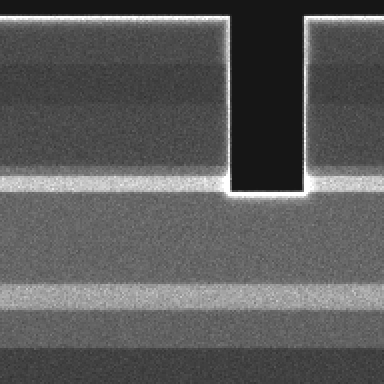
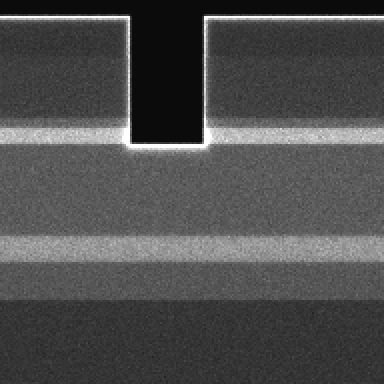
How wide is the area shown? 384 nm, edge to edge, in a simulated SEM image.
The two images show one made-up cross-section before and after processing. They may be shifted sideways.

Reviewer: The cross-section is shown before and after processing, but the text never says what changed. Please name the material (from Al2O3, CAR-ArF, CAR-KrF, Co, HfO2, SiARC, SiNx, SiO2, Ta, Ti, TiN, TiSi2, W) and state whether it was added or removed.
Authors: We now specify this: SiARC, removed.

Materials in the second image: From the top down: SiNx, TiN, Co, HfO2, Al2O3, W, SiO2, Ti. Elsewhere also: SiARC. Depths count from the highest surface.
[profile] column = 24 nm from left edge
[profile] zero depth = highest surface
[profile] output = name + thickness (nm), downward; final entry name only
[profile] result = SiNx 40, TiN 62, Co 10, HfO2 16, Al2O3 92, W 26, SiO2 38, Ti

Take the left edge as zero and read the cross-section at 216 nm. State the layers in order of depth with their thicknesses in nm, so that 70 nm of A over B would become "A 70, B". SiNx 40, TiN 62, Co 10, HfO2 16, Al2O3 92, W 26, SiO2 38, Ti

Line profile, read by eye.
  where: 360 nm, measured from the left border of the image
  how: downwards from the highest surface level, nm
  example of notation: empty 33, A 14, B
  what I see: SiNx 40, TiN 62, Co 10, HfO2 16, Al2O3 92, W 26, SiO2 38, Ti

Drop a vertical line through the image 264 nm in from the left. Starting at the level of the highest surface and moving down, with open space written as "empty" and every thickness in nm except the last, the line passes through SiNx 40, TiN 62, Co 10, HfO2 16, Al2O3 92, W 26, SiO2 38, Ti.